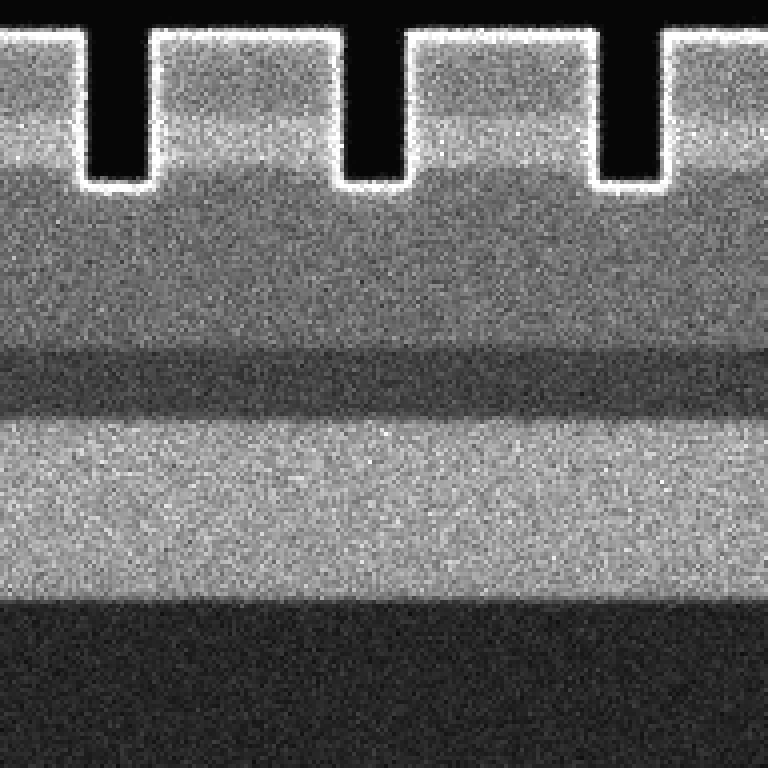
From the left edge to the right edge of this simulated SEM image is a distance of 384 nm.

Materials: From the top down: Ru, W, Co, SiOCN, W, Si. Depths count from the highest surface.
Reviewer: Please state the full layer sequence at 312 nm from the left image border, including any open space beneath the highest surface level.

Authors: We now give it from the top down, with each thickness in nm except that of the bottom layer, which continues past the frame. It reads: empty 76, Co 82, SiOCN 36, W 90, Si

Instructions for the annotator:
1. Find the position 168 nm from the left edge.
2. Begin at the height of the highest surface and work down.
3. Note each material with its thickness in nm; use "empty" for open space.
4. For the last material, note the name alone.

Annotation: Ru 42, W 26, Co 90, SiOCN 36, W 90, Si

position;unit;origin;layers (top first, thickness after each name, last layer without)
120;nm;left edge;Ru 42, W 26, Co 90, SiOCN 36, W 90, Si